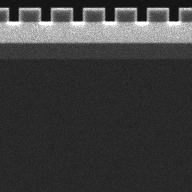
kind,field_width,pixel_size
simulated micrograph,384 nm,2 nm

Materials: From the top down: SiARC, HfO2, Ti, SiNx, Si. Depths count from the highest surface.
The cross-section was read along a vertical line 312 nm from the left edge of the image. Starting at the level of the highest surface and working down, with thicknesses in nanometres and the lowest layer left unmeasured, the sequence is SiARC 28, HfO2 42, Ti 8, SiNx 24, Si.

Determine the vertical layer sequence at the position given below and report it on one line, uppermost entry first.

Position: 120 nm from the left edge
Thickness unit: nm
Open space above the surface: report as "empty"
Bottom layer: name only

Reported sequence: SiARC 28, HfO2 42, Ti 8, SiNx 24, Si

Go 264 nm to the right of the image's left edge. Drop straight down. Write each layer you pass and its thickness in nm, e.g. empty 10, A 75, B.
SiARC 28, HfO2 42, Ti 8, SiNx 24, Si